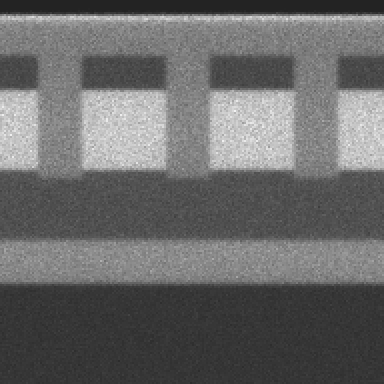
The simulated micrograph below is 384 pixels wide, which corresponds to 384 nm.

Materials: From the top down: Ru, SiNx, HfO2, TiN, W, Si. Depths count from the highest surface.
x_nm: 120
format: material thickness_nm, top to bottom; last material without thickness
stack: Ru 40, SiNx 34, HfO2 80, TiN 70, W 44, Si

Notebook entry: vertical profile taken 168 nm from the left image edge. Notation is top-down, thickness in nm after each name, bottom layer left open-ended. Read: Ru 162, TiN 62, W 44, Si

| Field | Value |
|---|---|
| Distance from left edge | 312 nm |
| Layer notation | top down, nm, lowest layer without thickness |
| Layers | Ru 162, TiN 62, W 44, Si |